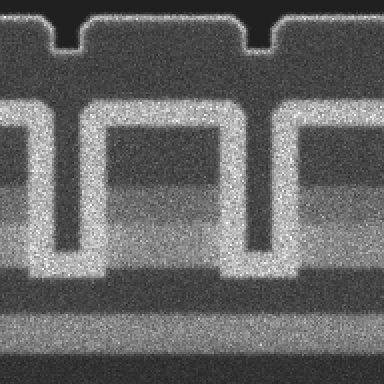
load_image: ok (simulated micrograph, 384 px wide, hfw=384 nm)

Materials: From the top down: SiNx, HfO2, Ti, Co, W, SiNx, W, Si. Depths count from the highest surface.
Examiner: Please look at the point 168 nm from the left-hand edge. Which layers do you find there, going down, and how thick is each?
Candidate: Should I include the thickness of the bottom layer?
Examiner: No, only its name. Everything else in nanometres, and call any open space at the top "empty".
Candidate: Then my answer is SiNx 84, HfO2 26, Ti 60, Co 38, W 44, SiNx 46, W 40, Si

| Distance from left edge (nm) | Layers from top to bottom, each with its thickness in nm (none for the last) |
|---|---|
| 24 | SiNx 84, HfO2 26, Ti 60, Co 38, W 44, SiNx 46, W 40, Si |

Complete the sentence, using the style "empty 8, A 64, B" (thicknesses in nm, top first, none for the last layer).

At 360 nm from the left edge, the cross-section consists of SiNx 84, HfO2 26, Ti 60, Co 38, W 44, SiNx 46, W 40, Si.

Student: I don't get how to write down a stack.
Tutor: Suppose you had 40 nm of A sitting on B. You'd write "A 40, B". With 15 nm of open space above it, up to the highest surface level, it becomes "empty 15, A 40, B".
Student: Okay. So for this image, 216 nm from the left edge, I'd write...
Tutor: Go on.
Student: SiNx 84, HfO2 26, Ti 60, Co 38, W 44, SiNx 46, W 40, Si